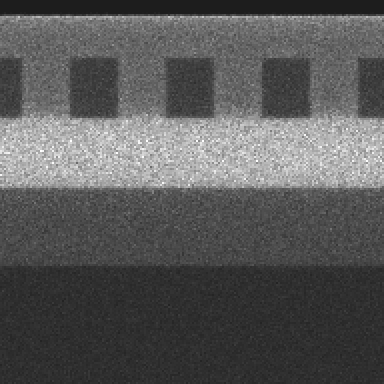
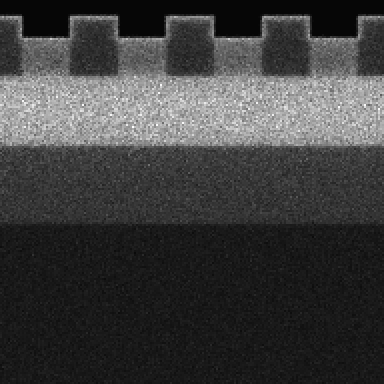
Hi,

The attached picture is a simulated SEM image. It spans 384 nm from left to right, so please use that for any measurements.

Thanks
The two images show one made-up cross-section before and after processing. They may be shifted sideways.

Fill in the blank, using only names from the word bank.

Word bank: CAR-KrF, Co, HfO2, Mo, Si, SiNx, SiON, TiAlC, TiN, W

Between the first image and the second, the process removed W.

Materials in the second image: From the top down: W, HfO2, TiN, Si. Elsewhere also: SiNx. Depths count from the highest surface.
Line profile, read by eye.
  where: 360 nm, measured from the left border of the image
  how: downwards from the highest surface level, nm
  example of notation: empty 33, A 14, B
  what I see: SiNx 60, HfO2 70, TiN 78, Si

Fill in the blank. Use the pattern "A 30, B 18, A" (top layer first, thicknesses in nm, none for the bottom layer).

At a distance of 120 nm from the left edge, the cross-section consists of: empty 22, W 38, HfO2 70, TiN 78, Si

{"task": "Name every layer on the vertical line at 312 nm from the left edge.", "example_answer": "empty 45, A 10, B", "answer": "empty 22, W 38, HfO2 70, TiN 78, Si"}